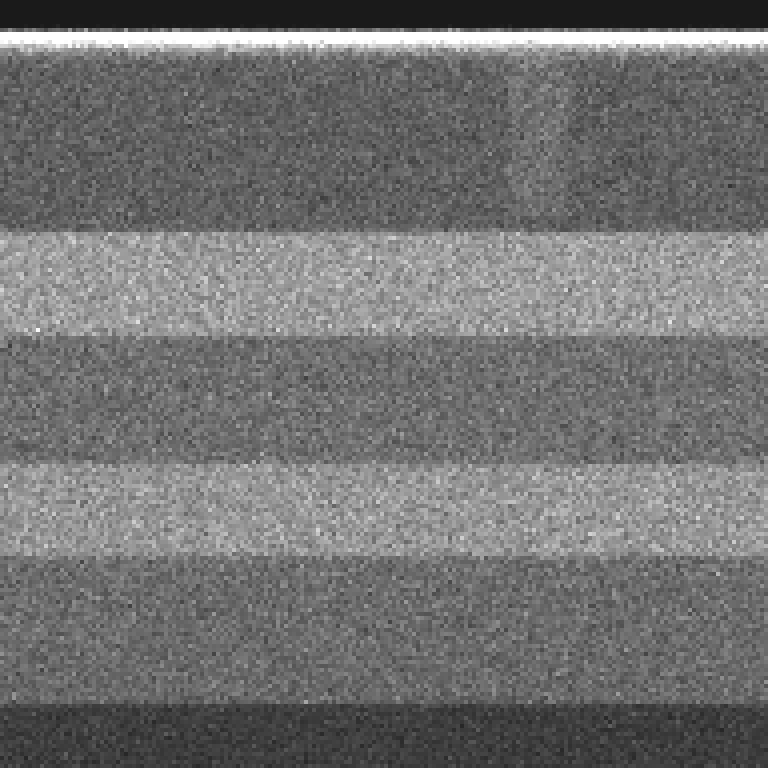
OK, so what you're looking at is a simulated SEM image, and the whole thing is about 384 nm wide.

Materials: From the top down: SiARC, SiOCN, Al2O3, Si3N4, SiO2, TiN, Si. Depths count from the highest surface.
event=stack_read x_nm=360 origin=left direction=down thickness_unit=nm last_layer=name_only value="SiARC 10, SiOCN 90, Al2O3 52, Si3N4 64, SiO2 46, TiN 74, Si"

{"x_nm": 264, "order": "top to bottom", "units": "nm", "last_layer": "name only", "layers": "SiARC 92, SiOCN 8, Al2O3 52, Si3N4 64, SiO2 46, TiN 74, Si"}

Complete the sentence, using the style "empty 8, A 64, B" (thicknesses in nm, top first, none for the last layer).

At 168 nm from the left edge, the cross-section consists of SiARC 10, SiOCN 90, Al2O3 52, Si3N4 64, SiO2 46, TiN 74, Si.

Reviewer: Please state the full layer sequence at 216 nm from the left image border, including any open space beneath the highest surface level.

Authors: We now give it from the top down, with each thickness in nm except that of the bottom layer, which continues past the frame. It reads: SiARC 10, SiOCN 90, Al2O3 52, Si3N4 64, SiO2 46, TiN 74, Si